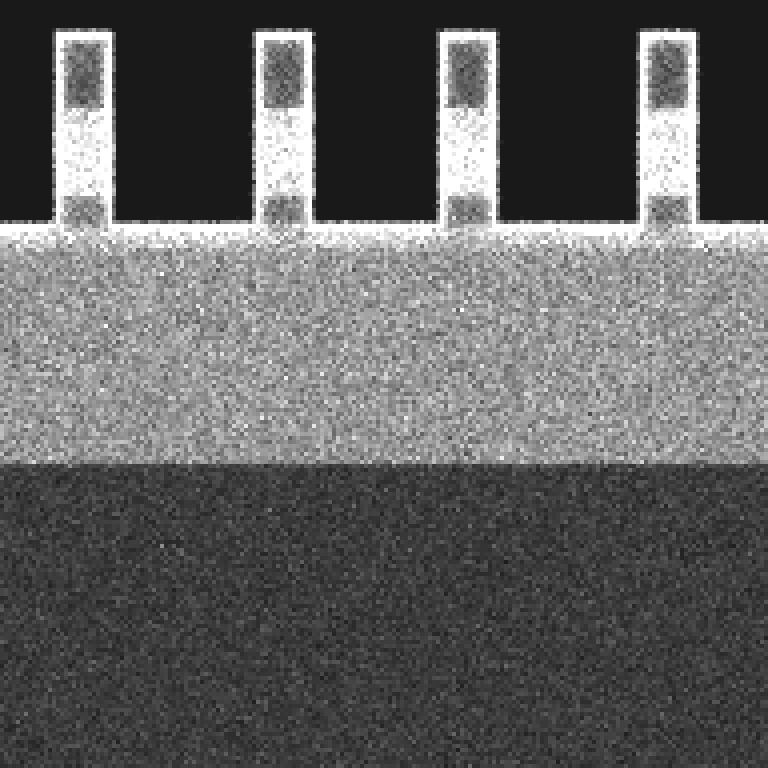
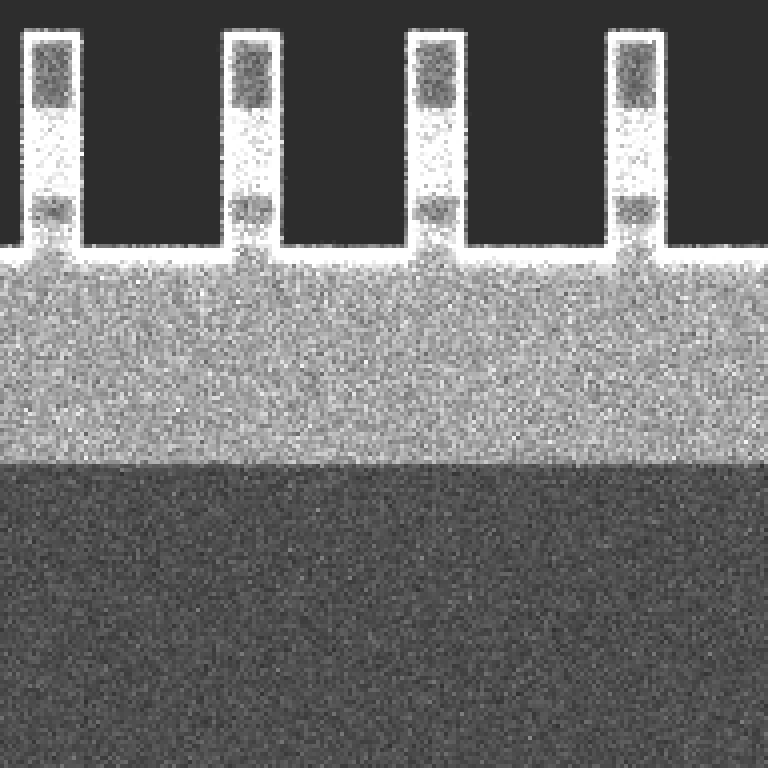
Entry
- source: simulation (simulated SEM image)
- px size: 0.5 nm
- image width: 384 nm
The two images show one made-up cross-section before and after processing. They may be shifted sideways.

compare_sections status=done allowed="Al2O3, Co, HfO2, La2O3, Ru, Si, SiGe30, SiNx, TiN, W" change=removed material="Ru"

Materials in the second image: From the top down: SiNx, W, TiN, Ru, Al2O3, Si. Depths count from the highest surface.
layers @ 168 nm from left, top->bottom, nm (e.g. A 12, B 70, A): empty 108, Al2O3 108, Si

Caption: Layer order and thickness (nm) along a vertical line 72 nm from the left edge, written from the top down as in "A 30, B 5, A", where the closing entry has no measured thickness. empty 108, Al2O3 108, Si